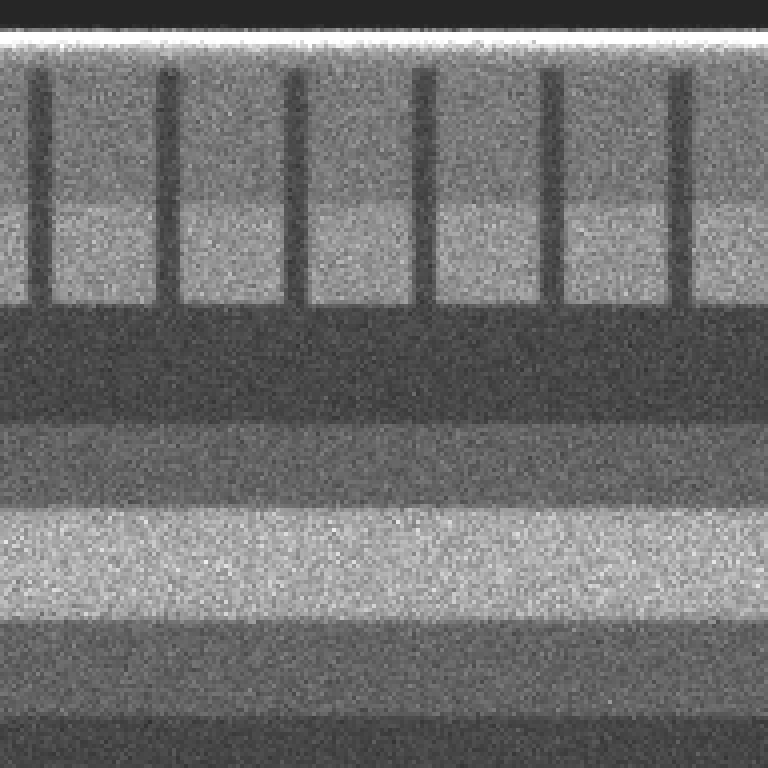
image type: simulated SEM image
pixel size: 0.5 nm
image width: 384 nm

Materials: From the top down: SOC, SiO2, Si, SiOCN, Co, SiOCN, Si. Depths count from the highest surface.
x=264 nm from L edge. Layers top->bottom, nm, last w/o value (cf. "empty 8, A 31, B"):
SOC 86, SiO2 50, Si 60, SiOCN 42, Co 56, SiOCN 48, Si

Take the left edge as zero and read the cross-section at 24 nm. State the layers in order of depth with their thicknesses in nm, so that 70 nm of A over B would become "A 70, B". SOC 18, Si 178, SiOCN 42, Co 56, SiOCN 48, Si